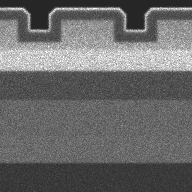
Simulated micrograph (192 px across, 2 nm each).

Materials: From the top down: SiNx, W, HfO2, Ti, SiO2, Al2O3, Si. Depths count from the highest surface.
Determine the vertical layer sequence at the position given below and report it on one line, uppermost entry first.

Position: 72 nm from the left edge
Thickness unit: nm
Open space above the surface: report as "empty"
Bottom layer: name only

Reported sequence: empty 44, SiNx 24, W 16, HfO2 42, Ti 58, SiO2 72, Al2O3 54, Si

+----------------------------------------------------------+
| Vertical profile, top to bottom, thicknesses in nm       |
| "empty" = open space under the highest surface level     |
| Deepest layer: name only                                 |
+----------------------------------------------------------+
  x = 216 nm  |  SiNx 24, W 60, HfO2 42, Ti 58, SiO2 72, Al2O3 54, Si